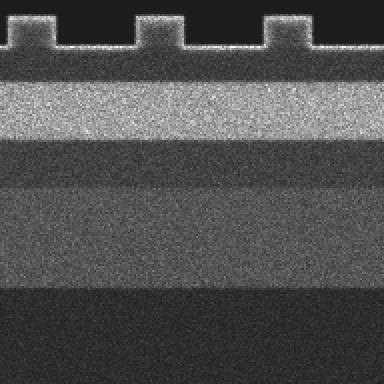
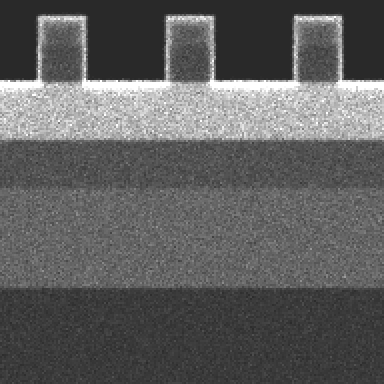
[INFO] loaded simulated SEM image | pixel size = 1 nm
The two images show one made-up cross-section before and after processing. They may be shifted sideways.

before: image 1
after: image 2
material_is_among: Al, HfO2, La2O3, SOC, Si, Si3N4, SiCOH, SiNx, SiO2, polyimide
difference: SiNx, removed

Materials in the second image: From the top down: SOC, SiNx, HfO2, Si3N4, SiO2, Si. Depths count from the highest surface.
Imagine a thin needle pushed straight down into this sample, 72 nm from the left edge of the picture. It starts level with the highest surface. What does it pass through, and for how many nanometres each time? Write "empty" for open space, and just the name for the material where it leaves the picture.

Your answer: SOC 30, SiNx 36, HfO2 58, Si3N4 48, SiO2 100, Si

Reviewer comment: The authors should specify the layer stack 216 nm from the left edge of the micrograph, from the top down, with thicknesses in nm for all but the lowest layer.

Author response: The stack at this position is empty 66, HfO2 58, Si3N4 48, SiO2 100, Si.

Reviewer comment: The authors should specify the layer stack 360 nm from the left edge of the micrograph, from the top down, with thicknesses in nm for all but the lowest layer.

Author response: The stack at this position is empty 66, HfO2 58, Si3N4 48, SiO2 100, Si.